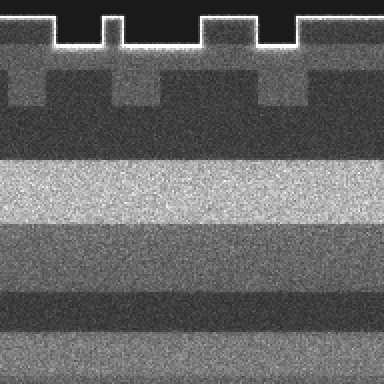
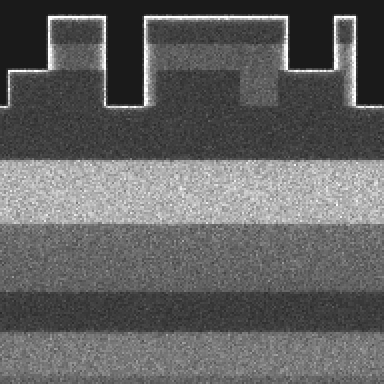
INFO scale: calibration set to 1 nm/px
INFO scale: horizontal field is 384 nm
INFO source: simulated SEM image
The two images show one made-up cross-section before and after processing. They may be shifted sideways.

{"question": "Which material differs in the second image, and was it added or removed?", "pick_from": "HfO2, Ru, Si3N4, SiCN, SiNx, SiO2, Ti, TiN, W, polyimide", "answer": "SiO2, removed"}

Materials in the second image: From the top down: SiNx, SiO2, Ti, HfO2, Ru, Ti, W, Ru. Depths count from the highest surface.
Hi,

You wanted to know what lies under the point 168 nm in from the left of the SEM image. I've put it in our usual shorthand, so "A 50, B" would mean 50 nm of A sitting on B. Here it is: SiNx 28, SiO2 26, Ti 90, HfO2 64, Ru 68, Ti 40, W 44, Ru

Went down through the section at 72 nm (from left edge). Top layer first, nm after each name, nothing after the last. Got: SiNx 28, SiO2 26, Ti 90, HfO2 64, Ru 68, Ti 40, W 44, Ru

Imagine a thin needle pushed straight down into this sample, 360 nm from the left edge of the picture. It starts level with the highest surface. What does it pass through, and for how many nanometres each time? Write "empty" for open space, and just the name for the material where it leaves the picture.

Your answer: empty 90, Ti 54, HfO2 64, Ru 68, Ti 40, W 44, Ru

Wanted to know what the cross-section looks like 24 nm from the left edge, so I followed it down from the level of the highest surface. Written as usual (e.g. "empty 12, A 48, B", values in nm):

empty 54, Ti 90, HfO2 64, Ru 68, Ti 40, W 44, Ru